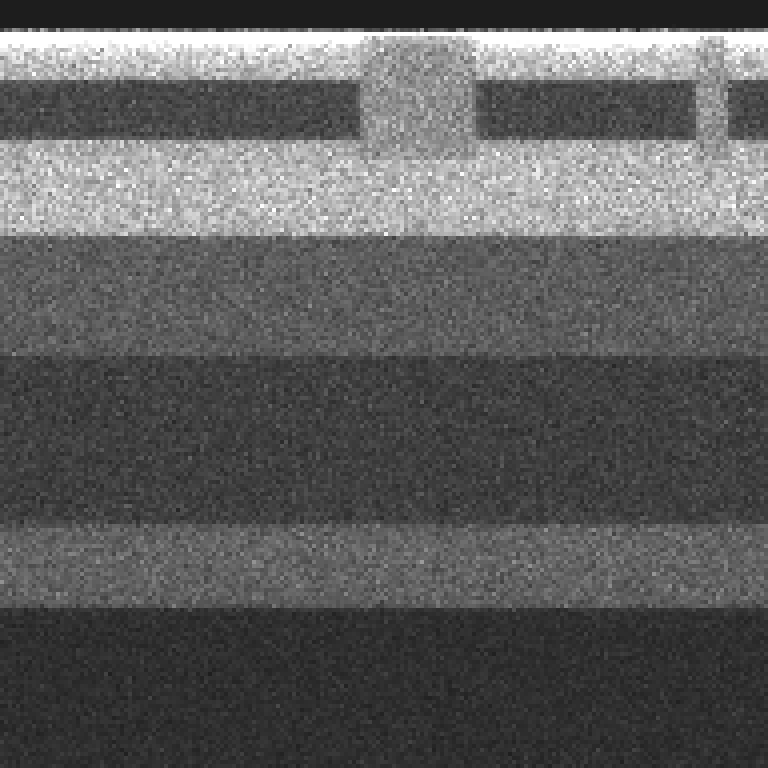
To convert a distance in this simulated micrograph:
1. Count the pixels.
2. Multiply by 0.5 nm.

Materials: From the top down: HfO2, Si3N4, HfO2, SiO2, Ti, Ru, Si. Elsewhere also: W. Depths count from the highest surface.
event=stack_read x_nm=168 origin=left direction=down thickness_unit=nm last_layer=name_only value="HfO2 24, Si3N4 30, HfO2 48, SiO2 60, Ti 84, Ru 42, Si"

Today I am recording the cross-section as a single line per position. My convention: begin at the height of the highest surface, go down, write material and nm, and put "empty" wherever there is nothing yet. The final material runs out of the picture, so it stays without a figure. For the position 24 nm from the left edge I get HfO2 24, Si3N4 30, HfO2 48, SiO2 60, Ti 84, Ru 42, Si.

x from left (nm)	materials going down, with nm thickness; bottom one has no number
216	W 64, HfO2 38, SiO2 60, Ti 84, Ru 42, Si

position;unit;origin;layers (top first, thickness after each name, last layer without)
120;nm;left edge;HfO2 24, Si3N4 30, HfO2 48, SiO2 60, Ti 84, Ru 42, Si